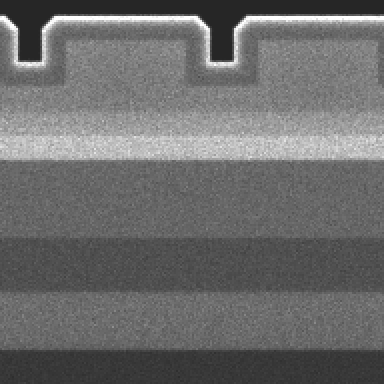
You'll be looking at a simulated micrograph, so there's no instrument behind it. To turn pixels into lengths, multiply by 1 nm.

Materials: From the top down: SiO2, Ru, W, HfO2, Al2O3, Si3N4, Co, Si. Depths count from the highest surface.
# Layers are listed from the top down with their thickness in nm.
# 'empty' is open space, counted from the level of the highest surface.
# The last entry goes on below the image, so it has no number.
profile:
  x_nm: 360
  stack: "SiO2 24, Ru 72, W 24, HfO2 24, Al2O3 78, Si3N4 54, Co 58, Si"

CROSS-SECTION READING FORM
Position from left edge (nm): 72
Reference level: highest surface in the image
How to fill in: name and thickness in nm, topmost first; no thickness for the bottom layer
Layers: SiO2 24, Ru 72, W 24, HfO2 24, Al2O3 78, Si3N4 54, Co 58, Si